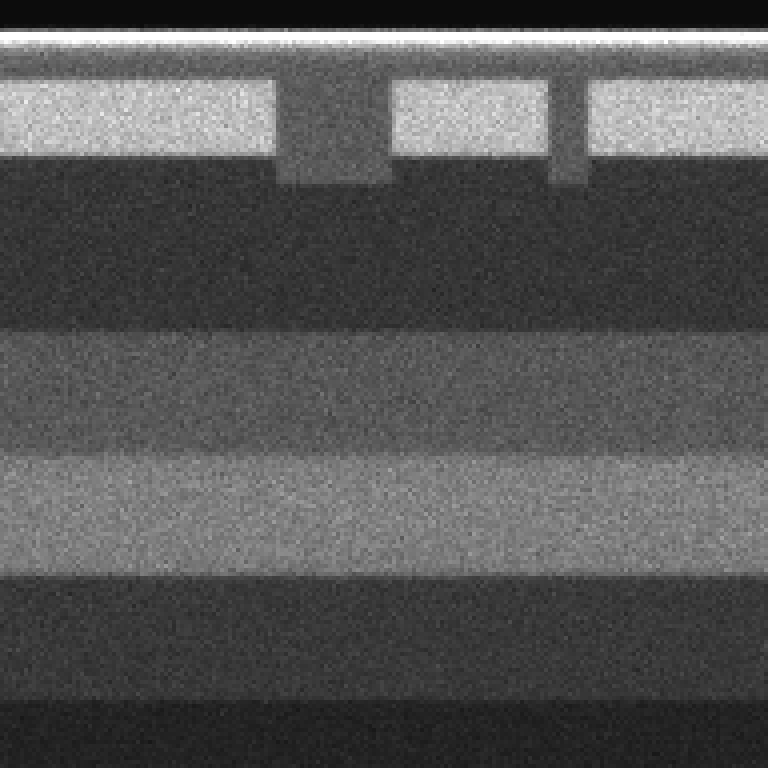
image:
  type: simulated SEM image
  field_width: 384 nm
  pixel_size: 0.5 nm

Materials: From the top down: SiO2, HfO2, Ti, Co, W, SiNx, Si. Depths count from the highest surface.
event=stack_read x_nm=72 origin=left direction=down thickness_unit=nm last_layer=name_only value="SiO2 24, HfO2 38, Ti 88, Co 62, W 60, SiNx 62, Si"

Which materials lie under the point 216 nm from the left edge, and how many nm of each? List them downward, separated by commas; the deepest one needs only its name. SiO2 24, HfO2 38, Ti 88, Co 62, W 60, SiNx 62, Si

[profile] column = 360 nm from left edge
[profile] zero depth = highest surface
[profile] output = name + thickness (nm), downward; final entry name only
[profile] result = SiO2 24, HfO2 38, Ti 88, Co 62, W 60, SiNx 62, Si